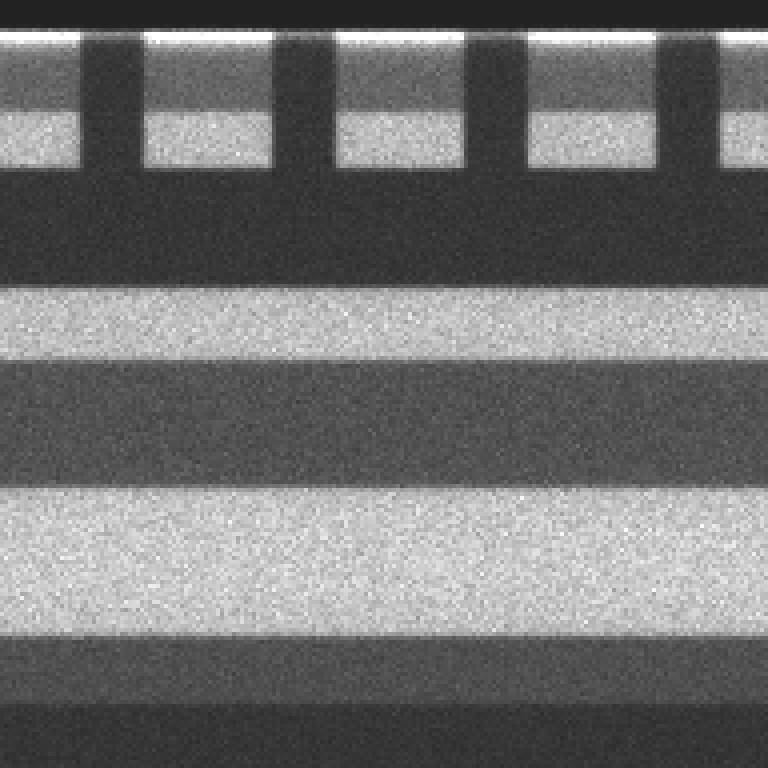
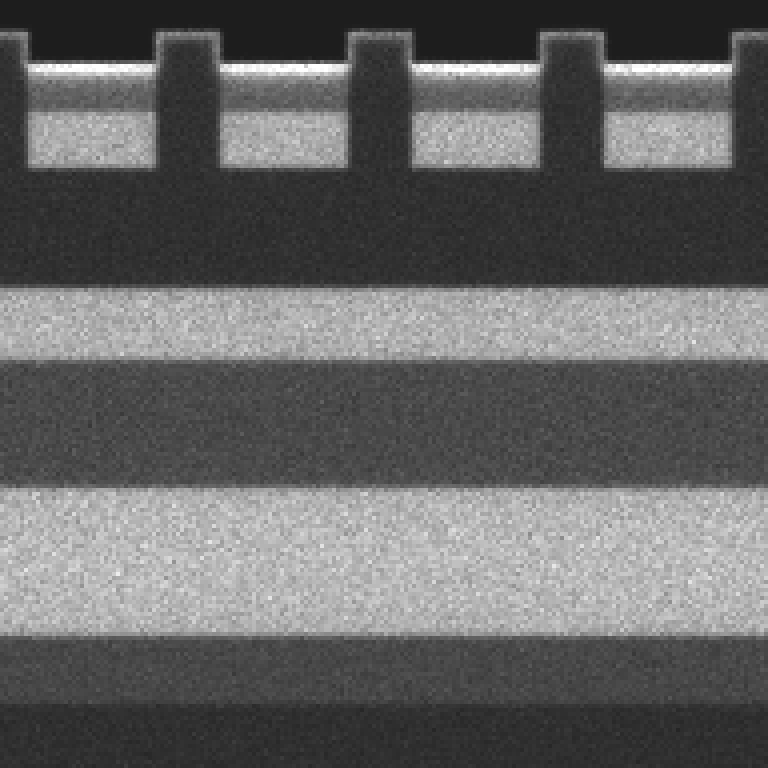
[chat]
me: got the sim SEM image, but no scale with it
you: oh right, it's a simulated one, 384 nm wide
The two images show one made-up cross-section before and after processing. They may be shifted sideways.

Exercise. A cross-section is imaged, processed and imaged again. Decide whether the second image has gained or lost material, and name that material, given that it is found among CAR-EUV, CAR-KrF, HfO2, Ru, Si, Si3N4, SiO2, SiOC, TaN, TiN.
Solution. removed: SiO2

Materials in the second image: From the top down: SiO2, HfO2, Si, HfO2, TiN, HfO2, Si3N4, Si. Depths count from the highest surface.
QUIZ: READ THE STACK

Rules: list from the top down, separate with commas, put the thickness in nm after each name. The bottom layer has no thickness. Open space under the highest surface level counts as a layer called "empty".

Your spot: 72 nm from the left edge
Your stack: empty 16, SiO2 24, HfO2 28, Si 60, HfO2 36, TiN 64, HfO2 74, Si3N4 34, Si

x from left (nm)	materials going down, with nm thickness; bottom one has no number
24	empty 16, SiO2 24, HfO2 28, Si 60, HfO2 36, TiN 64, HfO2 74, Si3N4 34, Si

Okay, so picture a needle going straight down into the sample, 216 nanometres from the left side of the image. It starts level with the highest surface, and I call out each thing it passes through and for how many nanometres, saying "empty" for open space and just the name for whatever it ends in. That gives empty 16, SiO2 24, HfO2 28, Si 60, HfO2 36, TiN 64, HfO2 74, Si3N4 34, Si